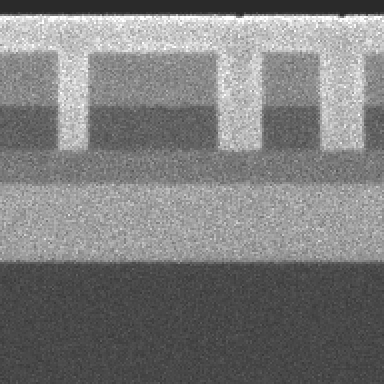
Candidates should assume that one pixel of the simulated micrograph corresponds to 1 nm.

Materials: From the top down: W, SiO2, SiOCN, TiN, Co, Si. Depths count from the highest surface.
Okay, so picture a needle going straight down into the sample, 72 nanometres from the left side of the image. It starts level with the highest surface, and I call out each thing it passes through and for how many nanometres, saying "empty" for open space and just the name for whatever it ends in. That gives W 134, TiN 34, Co 78, Si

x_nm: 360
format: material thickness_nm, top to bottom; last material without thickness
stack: W 134, TiN 34, Co 78, Si